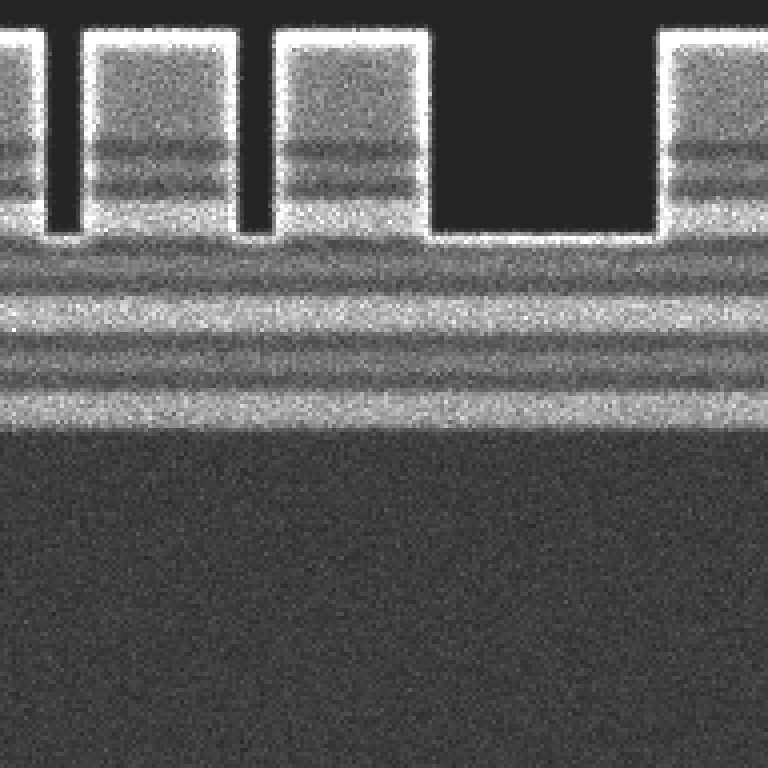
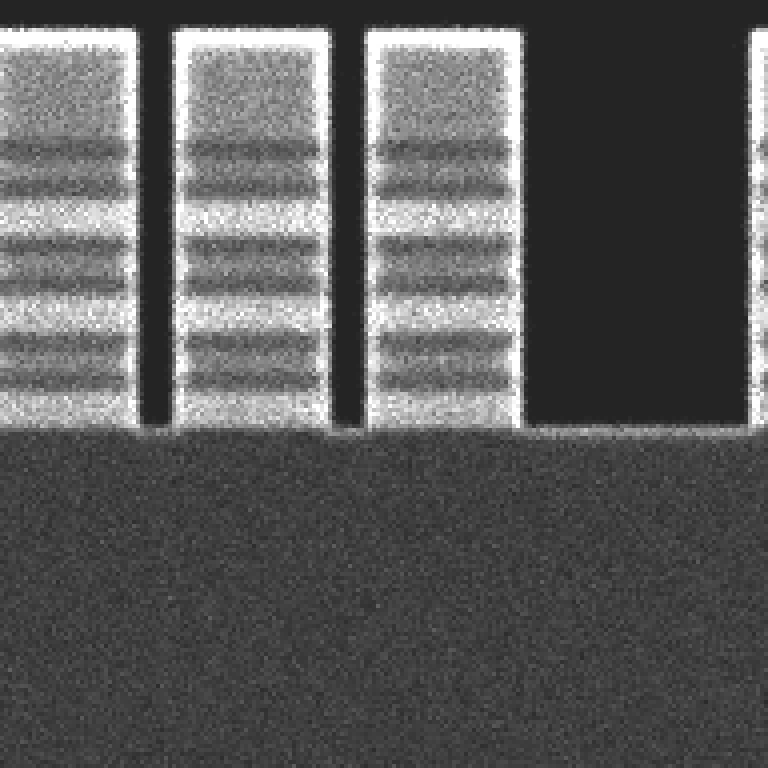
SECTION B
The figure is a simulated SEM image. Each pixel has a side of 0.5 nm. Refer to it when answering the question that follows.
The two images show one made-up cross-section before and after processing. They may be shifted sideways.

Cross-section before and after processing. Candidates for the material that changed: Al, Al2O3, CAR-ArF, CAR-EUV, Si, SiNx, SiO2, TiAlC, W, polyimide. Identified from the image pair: SiNx and SiO2 and W (removed).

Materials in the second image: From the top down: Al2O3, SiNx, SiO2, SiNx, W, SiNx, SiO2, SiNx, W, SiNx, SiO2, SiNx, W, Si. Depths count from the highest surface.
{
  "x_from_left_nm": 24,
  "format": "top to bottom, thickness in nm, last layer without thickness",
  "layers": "Al2O3 54, SiNx 10, SiO2 10, SiNx 10, W 18, SiNx 10, SiO2 10, SiNx 10, W 18, SiNx 10, SiO2 10, SiNx 10, W 18, Si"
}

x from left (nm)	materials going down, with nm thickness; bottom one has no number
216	Al2O3 54, SiNx 10, SiO2 10, SiNx 10, W 18, SiNx 10, SiO2 10, SiNx 10, W 18, SiNx 10, SiO2 10, SiNx 10, W 18, Si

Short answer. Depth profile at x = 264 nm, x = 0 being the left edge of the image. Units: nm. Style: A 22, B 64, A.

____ empty 198, Si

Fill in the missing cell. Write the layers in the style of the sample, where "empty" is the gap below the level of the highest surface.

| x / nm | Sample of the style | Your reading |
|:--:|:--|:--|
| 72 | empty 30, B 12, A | empty 198, Si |